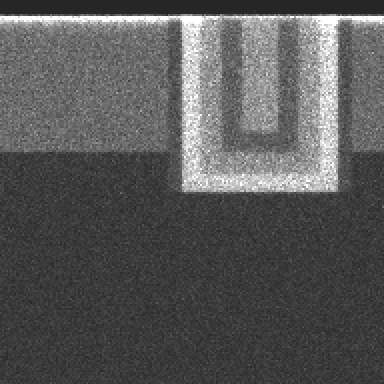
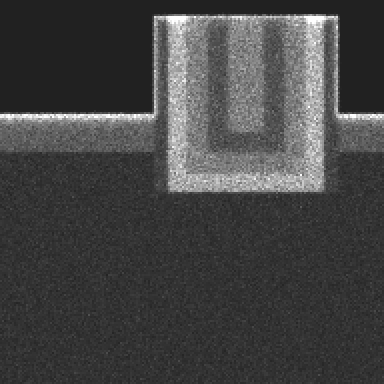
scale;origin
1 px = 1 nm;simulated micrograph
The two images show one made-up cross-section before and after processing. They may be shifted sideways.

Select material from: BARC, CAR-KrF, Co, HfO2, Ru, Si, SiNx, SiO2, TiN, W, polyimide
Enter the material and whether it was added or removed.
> SiO2 / removed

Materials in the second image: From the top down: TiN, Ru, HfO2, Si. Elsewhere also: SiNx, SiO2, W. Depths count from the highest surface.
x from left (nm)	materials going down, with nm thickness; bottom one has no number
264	TiN 136, Ru 22, HfO2 18, Si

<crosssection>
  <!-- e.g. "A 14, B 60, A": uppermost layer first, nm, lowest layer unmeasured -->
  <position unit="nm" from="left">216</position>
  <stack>TiN 136, Ru 22, HfO2 18, Si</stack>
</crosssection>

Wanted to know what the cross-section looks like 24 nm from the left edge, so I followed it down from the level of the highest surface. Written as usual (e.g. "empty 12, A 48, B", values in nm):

empty 98, SiO2 38, Si